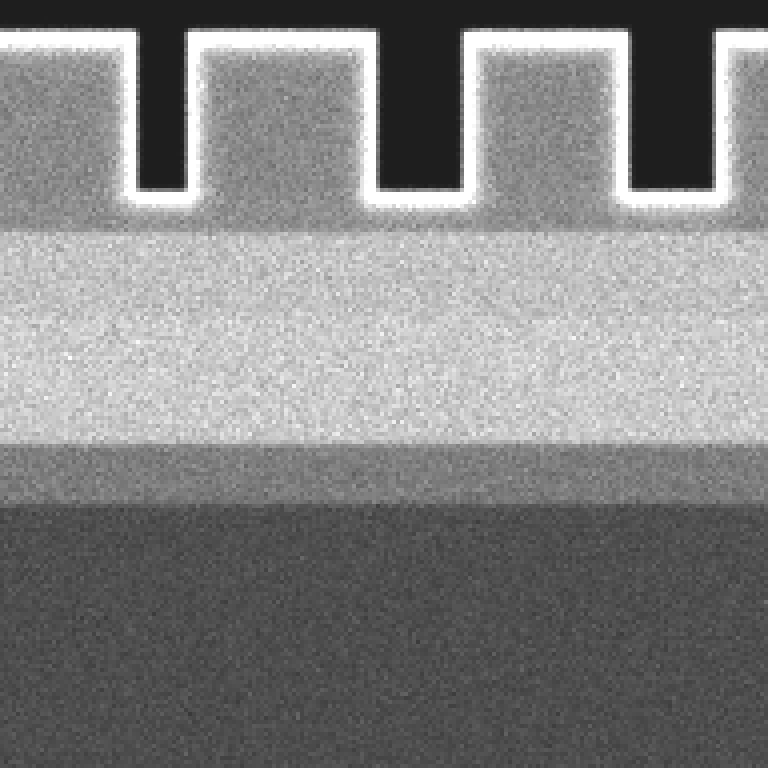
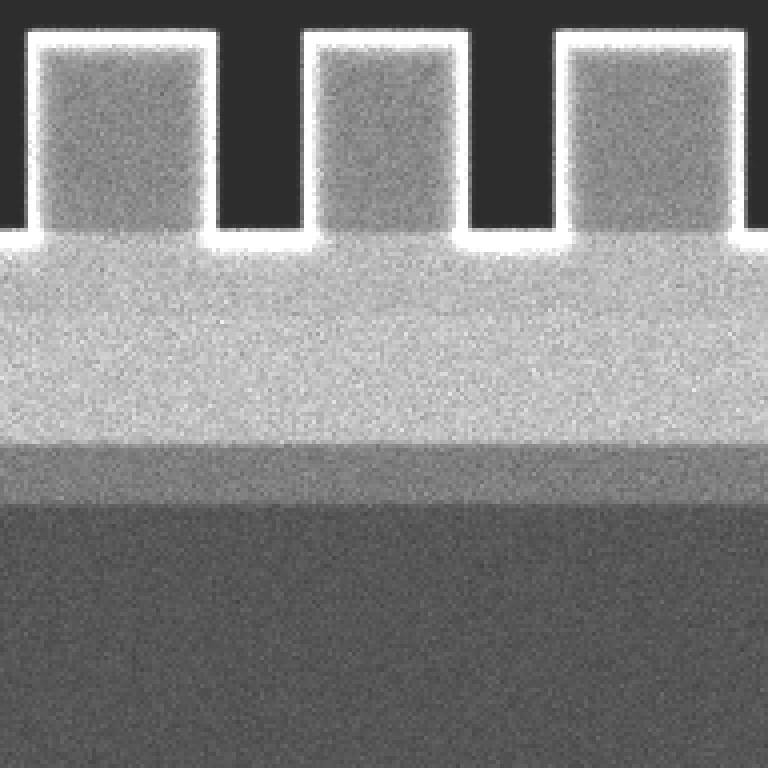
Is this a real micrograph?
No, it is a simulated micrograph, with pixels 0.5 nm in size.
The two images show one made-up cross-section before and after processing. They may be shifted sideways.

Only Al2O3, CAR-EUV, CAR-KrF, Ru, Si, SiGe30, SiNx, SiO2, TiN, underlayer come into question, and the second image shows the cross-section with underlayer removed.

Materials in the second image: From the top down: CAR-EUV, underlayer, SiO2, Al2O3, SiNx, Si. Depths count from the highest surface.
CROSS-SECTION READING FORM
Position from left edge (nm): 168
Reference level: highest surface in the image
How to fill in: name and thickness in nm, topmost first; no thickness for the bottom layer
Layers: CAR-EUV 80, underlayer 20, SiO2 42, Al2O3 64, SiNx 30, Si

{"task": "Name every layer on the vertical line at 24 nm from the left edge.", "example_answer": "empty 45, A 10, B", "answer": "CAR-EUV 80, underlayer 20, SiO2 42, Al2O3 64, SiNx 30, Si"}